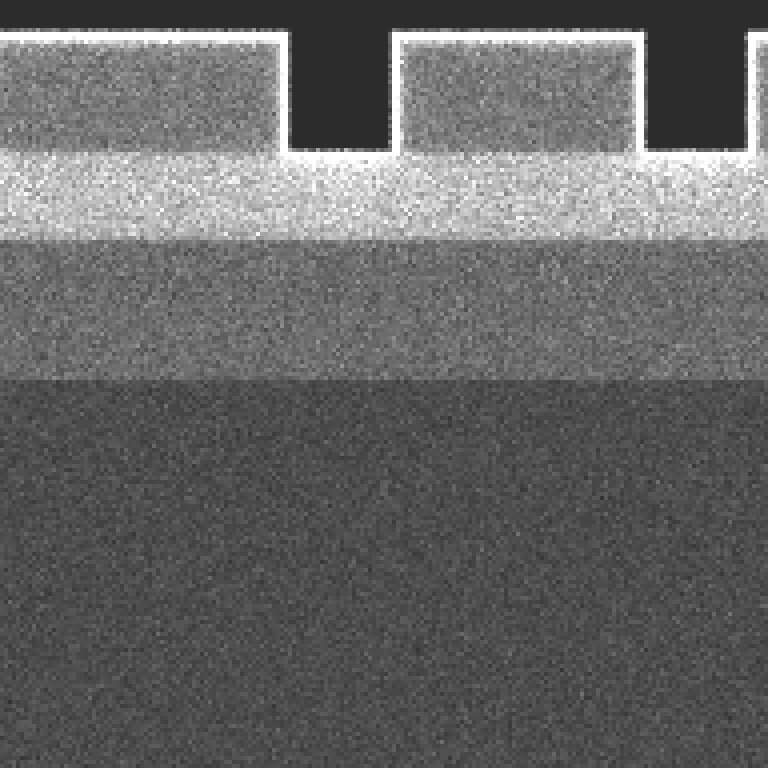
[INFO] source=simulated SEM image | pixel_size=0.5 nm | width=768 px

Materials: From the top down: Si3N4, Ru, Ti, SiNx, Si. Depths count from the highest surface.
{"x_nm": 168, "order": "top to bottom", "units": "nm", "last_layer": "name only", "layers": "empty 60, Ru 44, Ti 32, SiNx 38, Si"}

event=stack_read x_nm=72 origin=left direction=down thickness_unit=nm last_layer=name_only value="Si3N4 60, Ru 44, Ti 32, SiNx 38, Si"